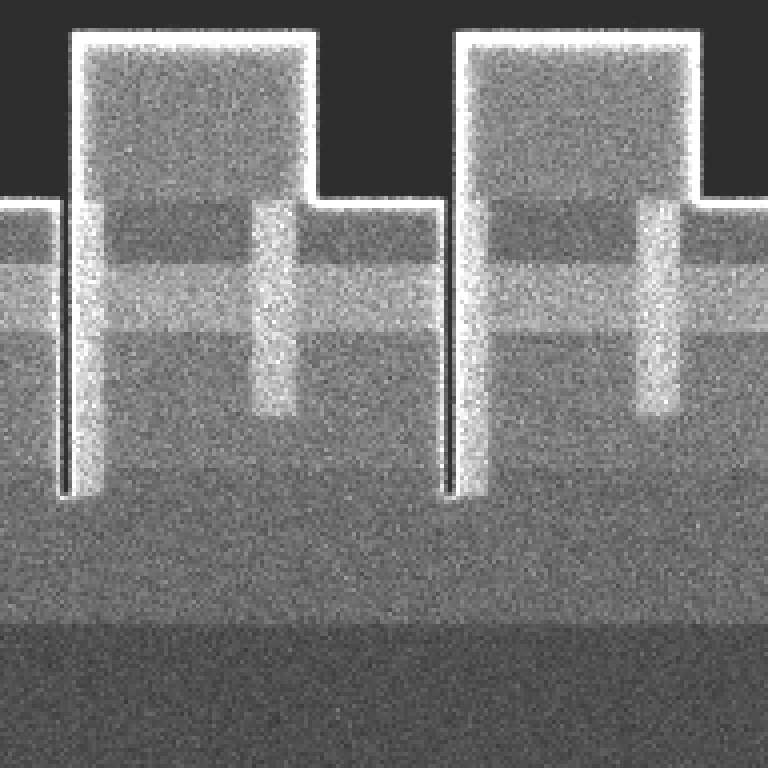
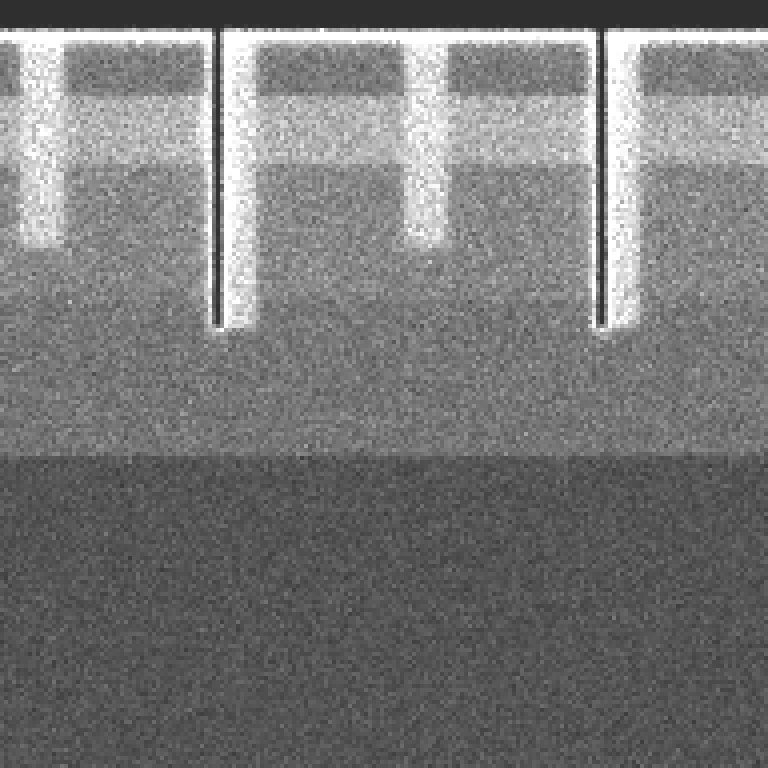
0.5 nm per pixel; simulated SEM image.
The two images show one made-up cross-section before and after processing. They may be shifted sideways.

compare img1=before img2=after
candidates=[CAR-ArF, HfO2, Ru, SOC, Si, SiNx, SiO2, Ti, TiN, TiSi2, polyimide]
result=removed:SOC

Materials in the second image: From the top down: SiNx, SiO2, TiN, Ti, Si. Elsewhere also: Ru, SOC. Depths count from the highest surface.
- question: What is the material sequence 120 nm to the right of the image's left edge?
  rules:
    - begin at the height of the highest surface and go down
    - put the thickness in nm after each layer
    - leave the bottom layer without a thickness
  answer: Ru 148, Ti 64, Si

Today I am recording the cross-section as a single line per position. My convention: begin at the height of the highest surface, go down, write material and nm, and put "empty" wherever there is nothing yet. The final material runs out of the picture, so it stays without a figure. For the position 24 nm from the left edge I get Ru 108, TiN 26, Ti 78, Si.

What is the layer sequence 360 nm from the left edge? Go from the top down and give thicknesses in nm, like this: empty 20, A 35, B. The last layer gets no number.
SiNx 32, SiO2 34, TiN 68, Ti 78, Si